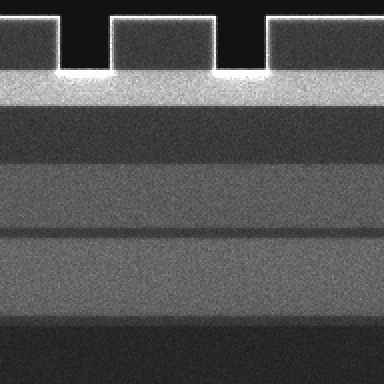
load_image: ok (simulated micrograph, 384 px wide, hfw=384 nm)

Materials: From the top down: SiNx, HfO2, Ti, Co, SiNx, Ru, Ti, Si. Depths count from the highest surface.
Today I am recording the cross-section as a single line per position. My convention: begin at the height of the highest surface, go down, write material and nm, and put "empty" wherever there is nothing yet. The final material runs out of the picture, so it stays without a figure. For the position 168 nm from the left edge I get SiNx 54, HfO2 36, Ti 58, Co 64, SiNx 10, Ru 78, Ti 10, Si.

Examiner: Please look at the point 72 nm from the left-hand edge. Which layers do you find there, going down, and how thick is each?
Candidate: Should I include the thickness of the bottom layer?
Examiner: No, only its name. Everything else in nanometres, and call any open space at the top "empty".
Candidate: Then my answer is empty 54, HfO2 36, Ti 58, Co 64, SiNx 10, Ru 78, Ti 10, Si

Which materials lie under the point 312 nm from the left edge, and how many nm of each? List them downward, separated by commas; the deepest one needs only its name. SiNx 54, HfO2 36, Ti 58, Co 64, SiNx 10, Ru 78, Ti 10, Si